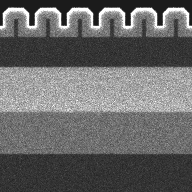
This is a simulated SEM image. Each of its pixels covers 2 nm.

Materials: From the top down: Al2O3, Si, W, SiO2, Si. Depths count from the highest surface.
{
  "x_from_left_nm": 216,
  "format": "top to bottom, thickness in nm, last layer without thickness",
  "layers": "Al2O3 58, Si 60, W 90, SiO2 84, Si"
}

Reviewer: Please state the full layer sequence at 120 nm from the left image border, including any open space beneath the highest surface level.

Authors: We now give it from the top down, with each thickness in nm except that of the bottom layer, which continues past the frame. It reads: empty 10, Al2O3 48, Si 60, W 90, SiO2 84, Si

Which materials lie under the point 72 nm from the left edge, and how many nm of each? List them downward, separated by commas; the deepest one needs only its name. empty 8, Al2O3 50, Si 60, W 90, SiO2 84, Si